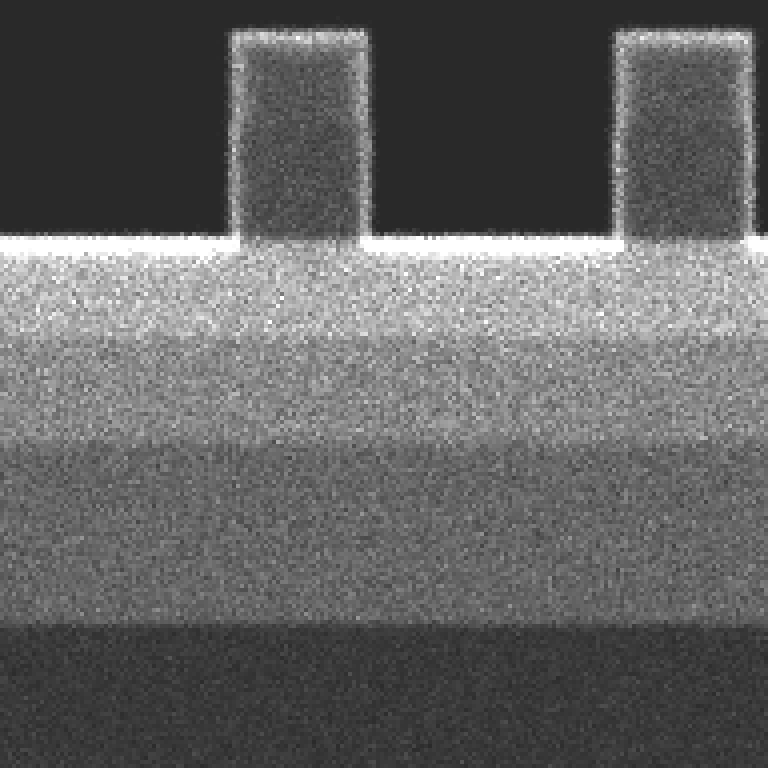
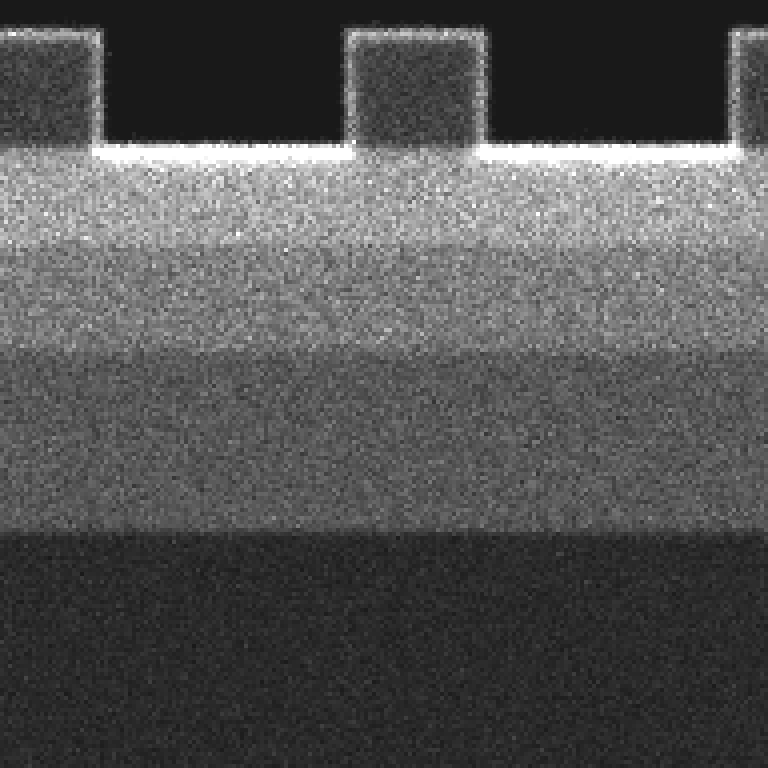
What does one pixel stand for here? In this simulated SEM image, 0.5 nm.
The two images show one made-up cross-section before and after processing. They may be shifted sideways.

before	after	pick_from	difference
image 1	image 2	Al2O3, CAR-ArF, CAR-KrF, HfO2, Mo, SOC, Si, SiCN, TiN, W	SOC removed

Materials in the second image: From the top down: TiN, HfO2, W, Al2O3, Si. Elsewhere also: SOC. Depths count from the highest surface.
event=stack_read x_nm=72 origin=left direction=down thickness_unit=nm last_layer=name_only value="empty 58, HfO2 48, W 54, Al2O3 90, Si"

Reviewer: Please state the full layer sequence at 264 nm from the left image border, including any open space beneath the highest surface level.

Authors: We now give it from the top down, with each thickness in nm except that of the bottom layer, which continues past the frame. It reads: empty 58, HfO2 48, W 54, Al2O3 90, Si